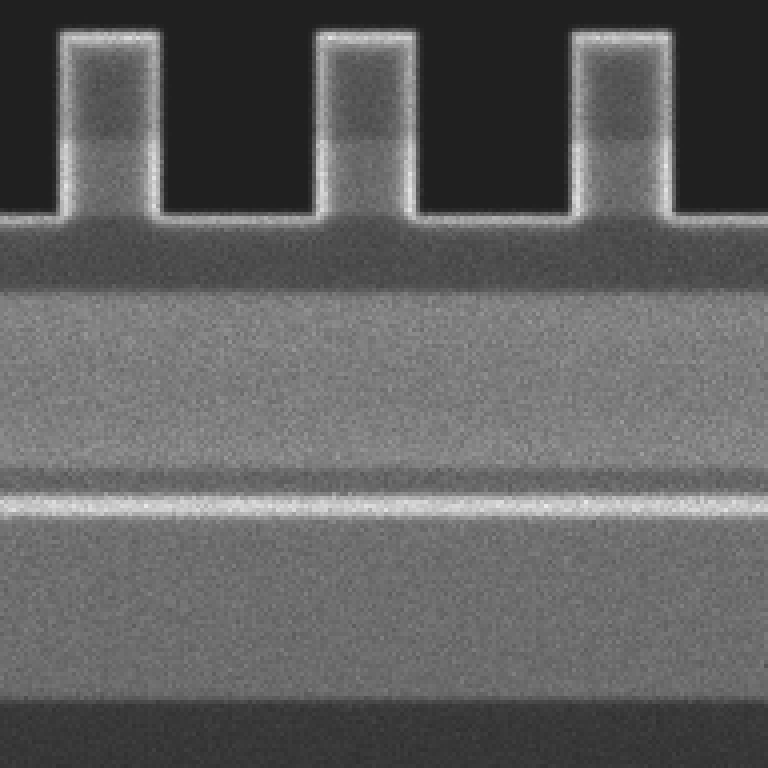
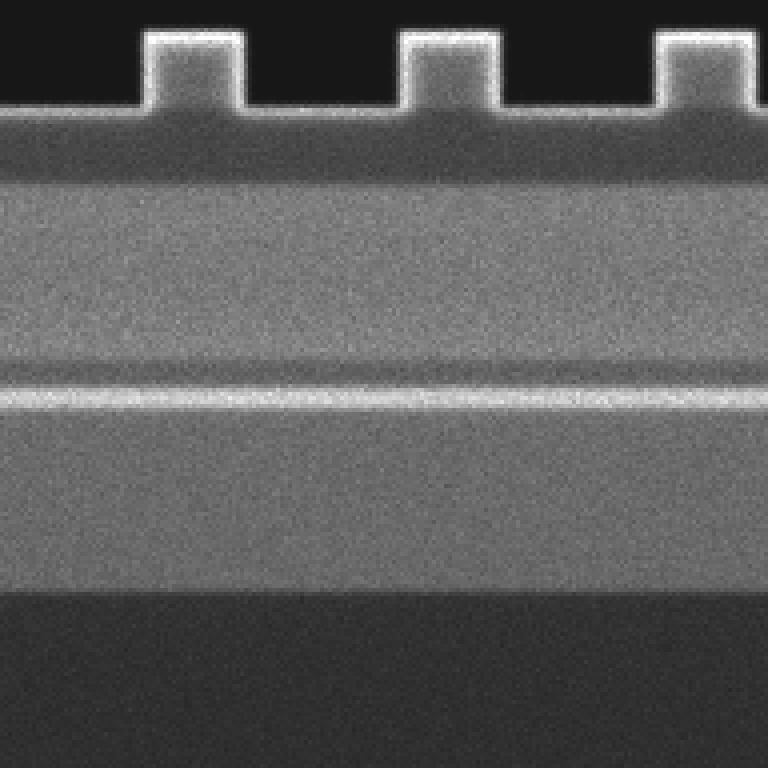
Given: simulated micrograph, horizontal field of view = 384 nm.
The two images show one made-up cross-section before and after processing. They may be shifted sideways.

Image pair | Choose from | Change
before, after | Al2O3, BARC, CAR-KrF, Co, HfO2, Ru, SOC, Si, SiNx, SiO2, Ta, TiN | SOC (removed)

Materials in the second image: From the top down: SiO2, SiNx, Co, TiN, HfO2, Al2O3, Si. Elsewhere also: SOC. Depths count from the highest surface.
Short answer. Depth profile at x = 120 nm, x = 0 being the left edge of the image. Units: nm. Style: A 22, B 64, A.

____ SiO2 38, SiNx 38, Co 88, TiN 14, HfO2 10, Al2O3 92, Si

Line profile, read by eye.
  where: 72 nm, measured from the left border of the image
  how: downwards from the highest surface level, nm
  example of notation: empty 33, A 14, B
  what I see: SiO2 38, SiNx 38, Co 88, TiN 14, HfO2 10, Al2O3 92, Si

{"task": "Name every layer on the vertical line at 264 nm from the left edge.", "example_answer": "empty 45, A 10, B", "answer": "empty 38, SiNx 38, Co 88, TiN 14, HfO2 10, Al2O3 92, Si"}